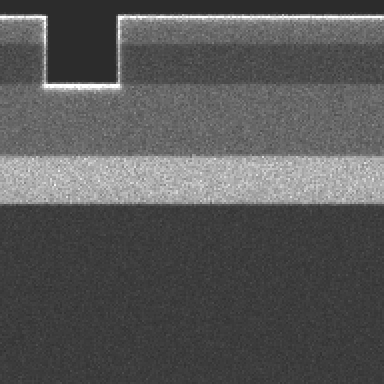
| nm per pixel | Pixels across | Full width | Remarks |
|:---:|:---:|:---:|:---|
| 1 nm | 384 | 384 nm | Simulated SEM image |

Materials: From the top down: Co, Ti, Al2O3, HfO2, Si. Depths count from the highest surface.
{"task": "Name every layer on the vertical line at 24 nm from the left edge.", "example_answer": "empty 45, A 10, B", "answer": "Co 28, Ti 40, Al2O3 72, HfO2 48, Si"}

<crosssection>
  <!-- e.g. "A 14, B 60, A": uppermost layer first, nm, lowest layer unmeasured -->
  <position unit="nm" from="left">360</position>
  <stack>Co 28, Ti 40, Al2O3 72, HfO2 48, Si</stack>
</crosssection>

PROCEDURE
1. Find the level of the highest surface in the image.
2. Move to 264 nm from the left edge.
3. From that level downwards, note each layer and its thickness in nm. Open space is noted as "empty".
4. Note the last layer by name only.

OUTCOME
Co 28, Ti 40, Al2O3 72, HfO2 48, Si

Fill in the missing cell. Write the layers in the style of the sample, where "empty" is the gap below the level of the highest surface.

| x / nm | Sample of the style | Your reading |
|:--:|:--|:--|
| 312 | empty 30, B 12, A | Co 28, Ti 40, Al2O3 72, HfO2 48, Si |